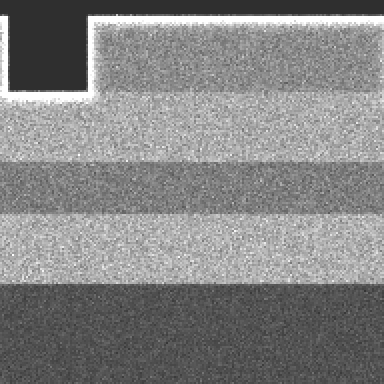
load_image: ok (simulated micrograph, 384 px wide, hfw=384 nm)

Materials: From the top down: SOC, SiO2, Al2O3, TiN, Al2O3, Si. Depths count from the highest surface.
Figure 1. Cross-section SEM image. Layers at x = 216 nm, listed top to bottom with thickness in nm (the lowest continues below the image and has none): SOC 76, SiO2 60, Al2O3 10, TiN 52, Al2O3 70, Si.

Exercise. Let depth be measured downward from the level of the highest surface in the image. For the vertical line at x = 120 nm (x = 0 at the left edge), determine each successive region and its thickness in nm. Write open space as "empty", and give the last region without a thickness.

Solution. SOC 76, SiO2 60, Al2O3 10, TiN 52, Al2O3 70, Si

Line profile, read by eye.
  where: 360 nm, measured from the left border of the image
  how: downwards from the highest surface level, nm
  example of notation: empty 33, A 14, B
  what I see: SOC 76, SiO2 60, Al2O3 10, TiN 52, Al2O3 70, Si